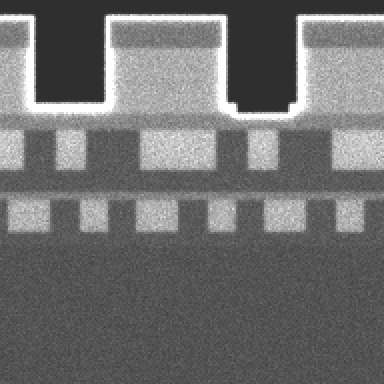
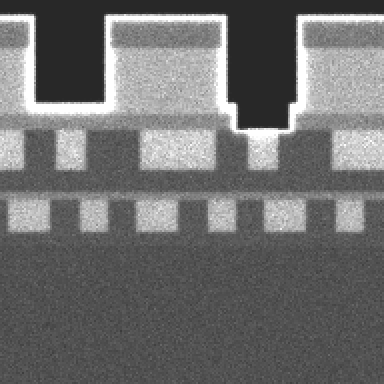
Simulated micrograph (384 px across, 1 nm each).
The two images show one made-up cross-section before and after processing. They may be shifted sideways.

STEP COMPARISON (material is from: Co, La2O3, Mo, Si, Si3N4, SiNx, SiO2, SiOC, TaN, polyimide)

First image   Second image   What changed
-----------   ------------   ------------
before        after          Si3N4, removed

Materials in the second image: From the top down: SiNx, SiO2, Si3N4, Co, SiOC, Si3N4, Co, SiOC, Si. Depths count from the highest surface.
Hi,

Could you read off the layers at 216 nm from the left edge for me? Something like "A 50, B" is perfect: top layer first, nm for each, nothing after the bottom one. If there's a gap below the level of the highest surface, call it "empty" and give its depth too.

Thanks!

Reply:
SiNx 32, SiO2 66, Si3N4 16, SiOC 62, Si3N4 8, Co 32, SiOC 14, Si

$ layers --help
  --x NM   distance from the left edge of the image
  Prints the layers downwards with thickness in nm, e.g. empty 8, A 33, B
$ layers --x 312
SiNx 32, SiO2 66, Si3N4 16, SiOC 62, Si3N4 8, SiOC 46, Si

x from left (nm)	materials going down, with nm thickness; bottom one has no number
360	SiNx 32, SiO2 66, Si3N4 16, Co 40, SiOC 22, Si3N4 8, Co 32, SiOC 14, Si